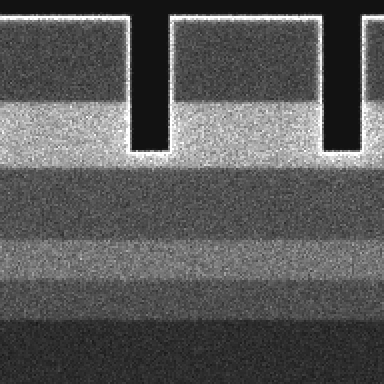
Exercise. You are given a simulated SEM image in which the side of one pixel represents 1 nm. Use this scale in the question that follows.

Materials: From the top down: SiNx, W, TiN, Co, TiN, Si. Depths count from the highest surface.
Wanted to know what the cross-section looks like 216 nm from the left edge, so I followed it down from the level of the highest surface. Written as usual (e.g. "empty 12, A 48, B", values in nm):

SiNx 86, W 66, TiN 72, Co 40, TiN 40, Si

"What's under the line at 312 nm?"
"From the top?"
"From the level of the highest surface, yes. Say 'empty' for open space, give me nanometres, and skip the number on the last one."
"SiNx 86, W 66, TiN 72, Co 40, TiN 40, Si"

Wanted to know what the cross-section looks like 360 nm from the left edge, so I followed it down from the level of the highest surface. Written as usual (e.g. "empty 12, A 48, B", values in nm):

empty 136, W 16, TiN 72, Co 40, TiN 40, Si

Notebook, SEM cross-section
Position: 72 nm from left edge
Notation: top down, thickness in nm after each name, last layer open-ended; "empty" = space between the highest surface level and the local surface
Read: SiNx 86, W 66, TiN 72, Co 40, TiN 40, Si